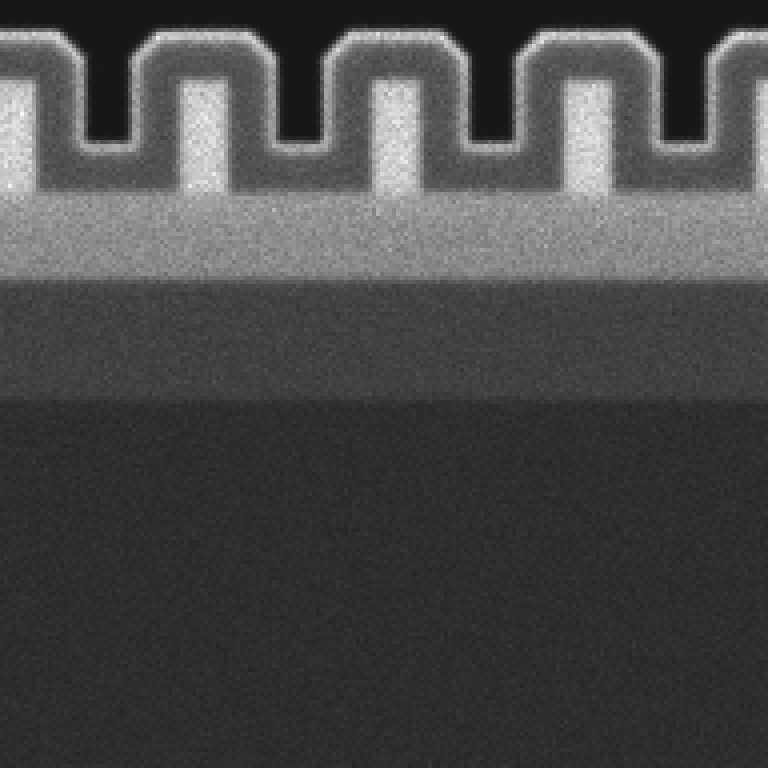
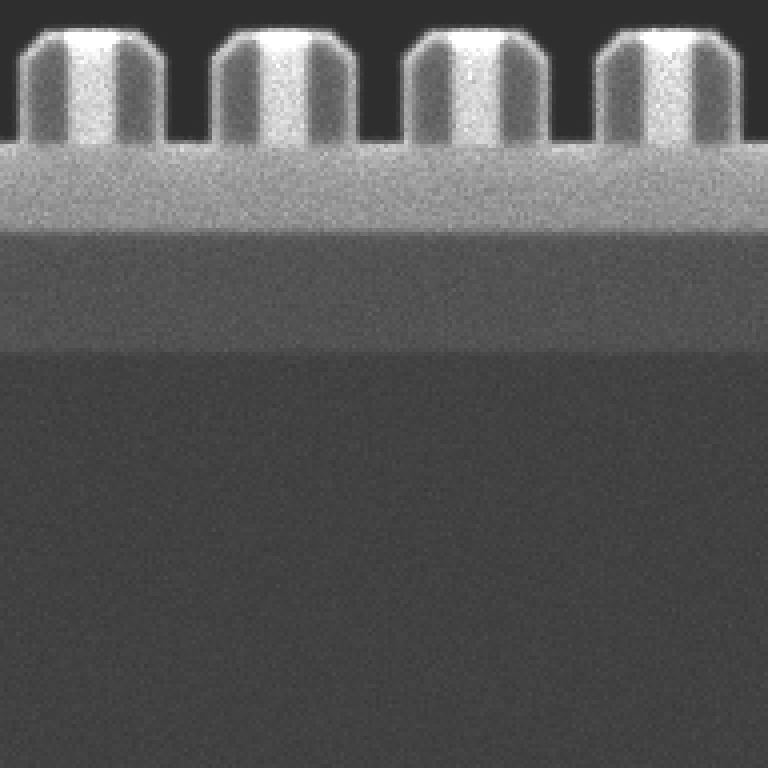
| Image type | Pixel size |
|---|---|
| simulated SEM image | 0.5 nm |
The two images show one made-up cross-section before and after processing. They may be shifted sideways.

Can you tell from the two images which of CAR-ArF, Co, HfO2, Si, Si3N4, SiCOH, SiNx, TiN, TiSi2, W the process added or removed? Yes, it removed Si3N4.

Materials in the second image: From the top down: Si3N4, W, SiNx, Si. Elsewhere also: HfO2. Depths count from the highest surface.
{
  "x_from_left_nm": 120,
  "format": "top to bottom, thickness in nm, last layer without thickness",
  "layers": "Si3N4 56, W 44, SiNx 60, Si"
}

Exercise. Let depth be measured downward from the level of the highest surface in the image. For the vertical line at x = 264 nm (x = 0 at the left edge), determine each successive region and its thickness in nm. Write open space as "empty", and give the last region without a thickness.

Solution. empty 4, Si3N4 52, W 44, SiNx 60, Si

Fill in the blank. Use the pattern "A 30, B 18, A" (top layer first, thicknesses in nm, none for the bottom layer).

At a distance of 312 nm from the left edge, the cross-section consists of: Si3N4 56, W 44, SiNx 60, Si